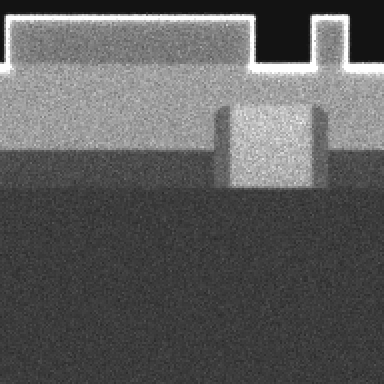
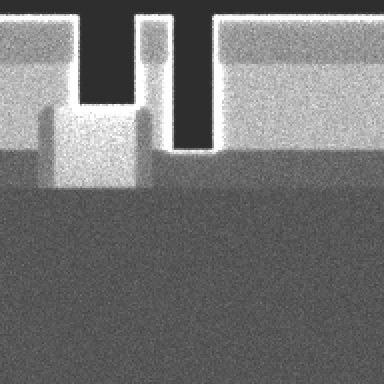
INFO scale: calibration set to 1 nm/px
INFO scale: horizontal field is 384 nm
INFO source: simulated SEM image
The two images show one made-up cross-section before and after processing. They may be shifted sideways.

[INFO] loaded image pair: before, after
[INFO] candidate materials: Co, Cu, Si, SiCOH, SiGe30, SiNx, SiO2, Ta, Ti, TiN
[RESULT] removed SiO2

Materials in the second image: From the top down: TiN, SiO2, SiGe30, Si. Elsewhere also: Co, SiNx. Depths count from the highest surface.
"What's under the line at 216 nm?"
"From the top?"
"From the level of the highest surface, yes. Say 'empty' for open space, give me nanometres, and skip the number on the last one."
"TiN 48, SiO2 86, SiGe30 38, Si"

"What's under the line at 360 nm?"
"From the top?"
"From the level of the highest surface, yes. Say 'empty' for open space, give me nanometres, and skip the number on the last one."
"TiN 48, SiO2 86, SiGe30 38, Si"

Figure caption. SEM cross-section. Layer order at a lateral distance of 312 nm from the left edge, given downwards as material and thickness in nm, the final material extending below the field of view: TiN 48, SiO2 86, SiGe30 38, Si